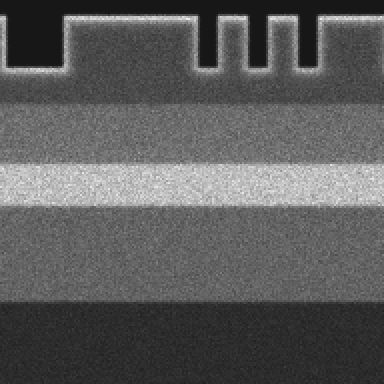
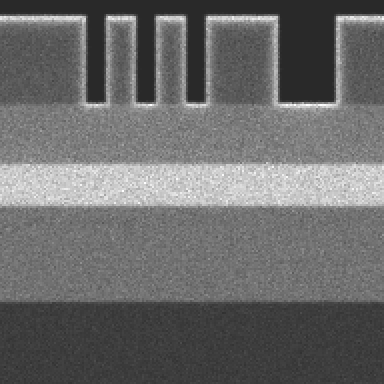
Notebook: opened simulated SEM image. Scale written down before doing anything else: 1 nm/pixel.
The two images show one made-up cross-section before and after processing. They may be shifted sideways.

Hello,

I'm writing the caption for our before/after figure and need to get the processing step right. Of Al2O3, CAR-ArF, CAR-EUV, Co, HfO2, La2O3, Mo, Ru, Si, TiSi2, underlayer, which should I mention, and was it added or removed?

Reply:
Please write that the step removed underlayer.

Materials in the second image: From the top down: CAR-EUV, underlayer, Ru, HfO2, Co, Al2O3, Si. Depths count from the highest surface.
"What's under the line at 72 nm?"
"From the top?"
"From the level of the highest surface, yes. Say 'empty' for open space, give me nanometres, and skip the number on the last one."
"CAR-EUV 52, underlayer 36, Ru 60, HfO2 42, Co 20, Al2O3 76, Si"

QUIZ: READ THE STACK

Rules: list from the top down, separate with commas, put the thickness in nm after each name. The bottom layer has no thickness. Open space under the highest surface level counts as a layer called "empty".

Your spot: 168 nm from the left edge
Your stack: CAR-EUV 52, underlayer 36, Ru 60, HfO2 42, Co 20, Al2O3 76, Si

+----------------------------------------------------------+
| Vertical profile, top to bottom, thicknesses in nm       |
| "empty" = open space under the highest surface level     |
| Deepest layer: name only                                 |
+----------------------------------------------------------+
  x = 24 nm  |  CAR-EUV 52, underlayer 36, Ru 60, HfO2 42, Co 20, Al2O3 76, Si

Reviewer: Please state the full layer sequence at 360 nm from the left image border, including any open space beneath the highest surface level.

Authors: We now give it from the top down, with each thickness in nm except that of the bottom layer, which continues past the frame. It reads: CAR-EUV 52, underlayer 36, Ru 60, HfO2 42, Co 20, Al2O3 76, Si